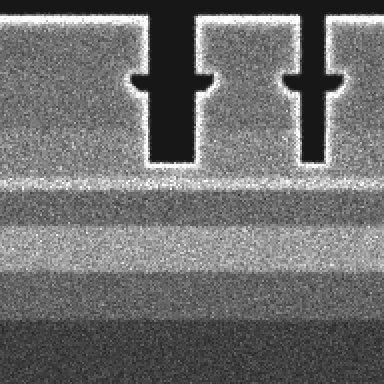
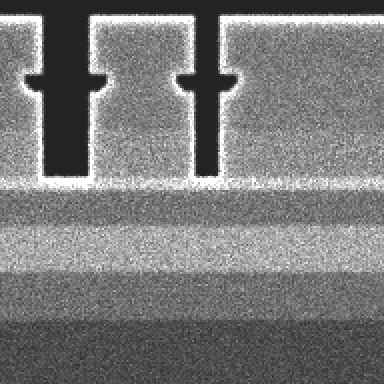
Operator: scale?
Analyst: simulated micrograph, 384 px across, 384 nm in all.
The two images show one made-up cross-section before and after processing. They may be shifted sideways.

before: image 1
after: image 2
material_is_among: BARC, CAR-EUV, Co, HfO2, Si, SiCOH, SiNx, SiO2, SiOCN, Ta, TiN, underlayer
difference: TiN, removed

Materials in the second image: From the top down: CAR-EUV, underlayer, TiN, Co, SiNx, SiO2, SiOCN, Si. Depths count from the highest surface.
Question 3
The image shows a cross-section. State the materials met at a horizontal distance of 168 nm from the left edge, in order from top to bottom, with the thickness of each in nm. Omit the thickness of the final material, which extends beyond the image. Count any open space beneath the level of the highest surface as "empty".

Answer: CAR-EUV 58, underlayer 56, TiN 48, Co 12, SiNx 36, SiO2 46, SiOCN 48, Si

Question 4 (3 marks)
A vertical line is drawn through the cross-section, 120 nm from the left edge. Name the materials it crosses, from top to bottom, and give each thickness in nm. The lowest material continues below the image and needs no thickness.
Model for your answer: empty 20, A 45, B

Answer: CAR-EUV 58, underlayer 56, TiN 48, Co 12, SiNx 36, SiO2 46, SiOCN 48, Si